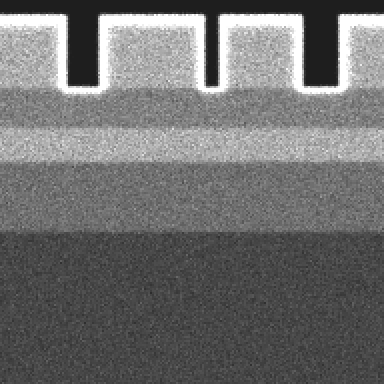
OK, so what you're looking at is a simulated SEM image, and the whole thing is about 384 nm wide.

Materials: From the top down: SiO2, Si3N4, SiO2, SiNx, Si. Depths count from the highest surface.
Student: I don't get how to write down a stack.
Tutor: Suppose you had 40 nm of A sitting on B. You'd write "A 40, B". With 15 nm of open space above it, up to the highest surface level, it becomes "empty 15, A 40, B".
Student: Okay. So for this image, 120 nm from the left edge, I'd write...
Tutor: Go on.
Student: SiO2 72, Si3N4 40, SiO2 34, SiNx 70, Si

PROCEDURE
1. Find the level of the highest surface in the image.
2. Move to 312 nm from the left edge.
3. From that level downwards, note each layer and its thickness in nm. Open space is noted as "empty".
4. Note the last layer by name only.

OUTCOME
empty 72, Si3N4 40, SiO2 34, SiNx 70, Si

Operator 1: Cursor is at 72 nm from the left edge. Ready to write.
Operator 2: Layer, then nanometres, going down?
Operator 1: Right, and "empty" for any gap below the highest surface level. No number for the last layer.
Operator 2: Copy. empty 72, Si3N4 40, SiO2 34, SiNx 70, Si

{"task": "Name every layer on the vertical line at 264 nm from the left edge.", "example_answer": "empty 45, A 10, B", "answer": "SiO2 72, Si3N4 40, SiO2 34, SiNx 70, Si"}